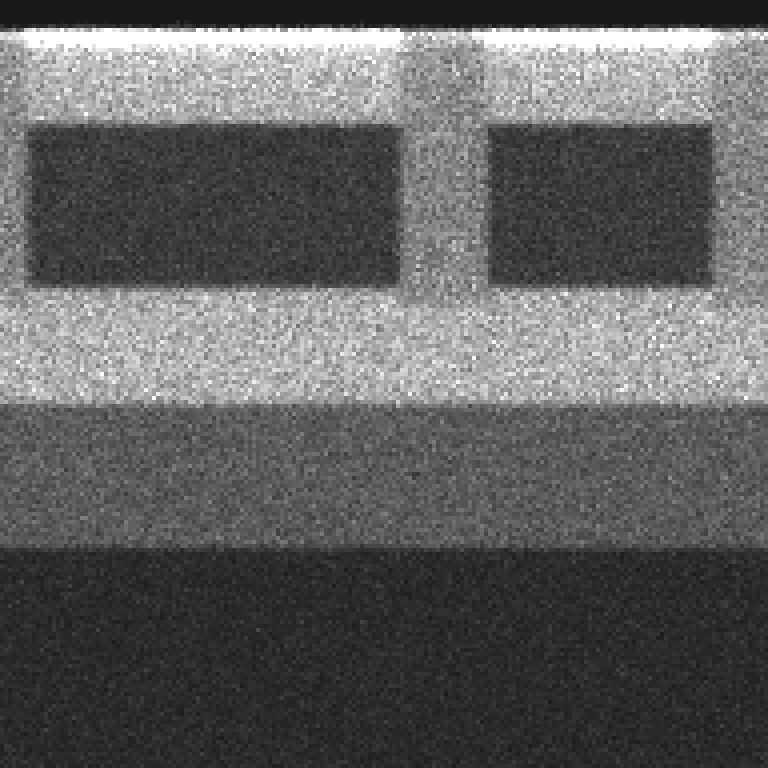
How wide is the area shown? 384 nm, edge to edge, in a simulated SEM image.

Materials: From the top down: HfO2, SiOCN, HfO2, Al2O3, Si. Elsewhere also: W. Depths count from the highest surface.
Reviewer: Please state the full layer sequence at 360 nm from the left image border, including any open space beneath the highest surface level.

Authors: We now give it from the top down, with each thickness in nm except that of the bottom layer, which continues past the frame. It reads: W 138, HfO2 48, Al2O3 72, Si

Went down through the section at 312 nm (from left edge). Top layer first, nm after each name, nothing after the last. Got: HfO2 46, SiOCN 82, HfO2 58, Al2O3 72, Si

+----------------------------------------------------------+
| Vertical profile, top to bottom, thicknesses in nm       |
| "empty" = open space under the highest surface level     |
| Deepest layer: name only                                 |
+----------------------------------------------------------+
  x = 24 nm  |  HfO2 46, SiOCN 82, HfO2 58, Al2O3 72, Si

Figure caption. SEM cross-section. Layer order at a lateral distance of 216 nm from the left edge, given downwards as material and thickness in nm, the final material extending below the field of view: W 138, HfO2 48, Al2O3 72, Si